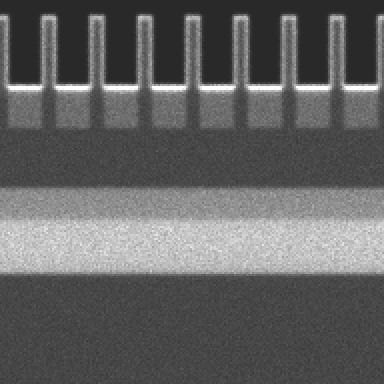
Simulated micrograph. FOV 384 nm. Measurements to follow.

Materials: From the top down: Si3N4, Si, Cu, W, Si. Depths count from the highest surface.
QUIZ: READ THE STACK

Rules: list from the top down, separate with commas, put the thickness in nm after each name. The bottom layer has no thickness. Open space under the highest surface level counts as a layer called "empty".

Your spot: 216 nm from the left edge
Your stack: empty 70, Si3N4 42, Si 60, Cu 32, W 54, Si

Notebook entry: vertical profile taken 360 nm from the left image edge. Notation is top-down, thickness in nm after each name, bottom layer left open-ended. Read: empty 70, Si3N4 42, Si 60, Cu 32, W 54, Si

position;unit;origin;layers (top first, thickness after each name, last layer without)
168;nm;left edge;empty 70, Si3N4 42, Si 60, Cu 32, W 54, Si